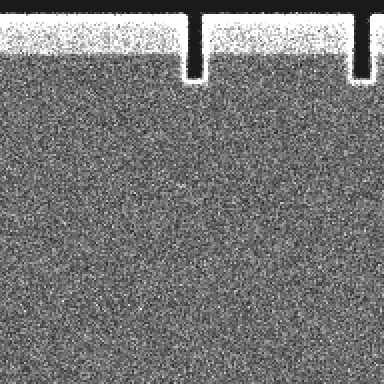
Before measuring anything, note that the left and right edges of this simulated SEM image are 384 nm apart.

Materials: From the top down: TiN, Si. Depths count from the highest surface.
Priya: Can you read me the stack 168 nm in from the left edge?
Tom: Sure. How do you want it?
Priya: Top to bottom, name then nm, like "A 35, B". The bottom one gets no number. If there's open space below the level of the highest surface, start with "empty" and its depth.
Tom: TiN 38, Si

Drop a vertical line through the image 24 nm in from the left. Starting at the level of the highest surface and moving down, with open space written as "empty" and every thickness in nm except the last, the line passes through TiN 38, Si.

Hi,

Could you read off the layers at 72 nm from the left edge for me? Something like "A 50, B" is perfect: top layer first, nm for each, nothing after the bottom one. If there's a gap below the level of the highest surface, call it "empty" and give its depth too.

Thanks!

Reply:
TiN 38, Si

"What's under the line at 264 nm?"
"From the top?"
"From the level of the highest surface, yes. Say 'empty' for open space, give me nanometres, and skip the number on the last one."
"TiN 38, Si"